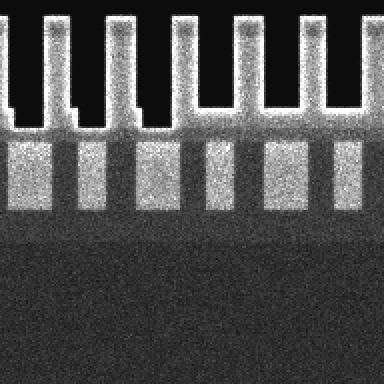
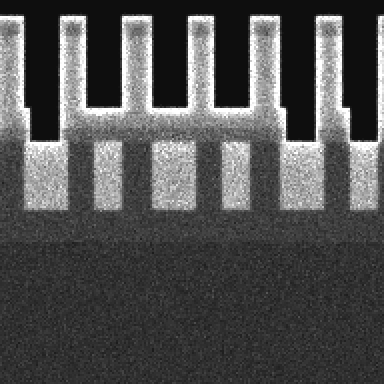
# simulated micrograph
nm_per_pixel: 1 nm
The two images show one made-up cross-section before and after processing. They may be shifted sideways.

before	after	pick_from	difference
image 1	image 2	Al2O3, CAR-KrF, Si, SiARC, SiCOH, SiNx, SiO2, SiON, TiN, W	SiNx removed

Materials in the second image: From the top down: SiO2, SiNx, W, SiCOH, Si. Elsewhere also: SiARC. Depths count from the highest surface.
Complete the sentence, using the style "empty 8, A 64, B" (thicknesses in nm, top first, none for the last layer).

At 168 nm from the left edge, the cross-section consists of empty 92, SiO2 20, SiNx 14, W 68, SiCOH 32, Si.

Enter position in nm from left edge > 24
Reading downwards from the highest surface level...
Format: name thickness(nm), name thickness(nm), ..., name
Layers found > empty 92, SiO2 20, SiNx 14, W 68, SiCOH 32, Si